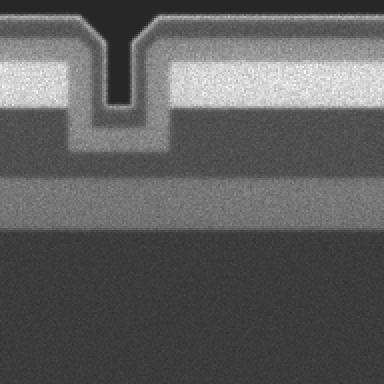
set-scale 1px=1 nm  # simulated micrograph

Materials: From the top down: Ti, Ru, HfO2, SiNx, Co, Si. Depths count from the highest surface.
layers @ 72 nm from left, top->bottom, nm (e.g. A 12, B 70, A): Ti 22, Ru 114, SiNx 26, Co 52, Si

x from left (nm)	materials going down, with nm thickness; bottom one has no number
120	empty 90, Ti 22, Ru 24, SiNx 26, Co 52, Si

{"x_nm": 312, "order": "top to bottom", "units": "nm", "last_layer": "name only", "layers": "Ti 22, Ru 24, HfO2 46, SiNx 70, Co 52, Si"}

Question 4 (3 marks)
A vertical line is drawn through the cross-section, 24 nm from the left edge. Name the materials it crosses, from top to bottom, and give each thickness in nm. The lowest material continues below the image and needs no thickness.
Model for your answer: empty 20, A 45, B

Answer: Ti 22, Ru 24, HfO2 46, SiNx 70, Co 52, Si